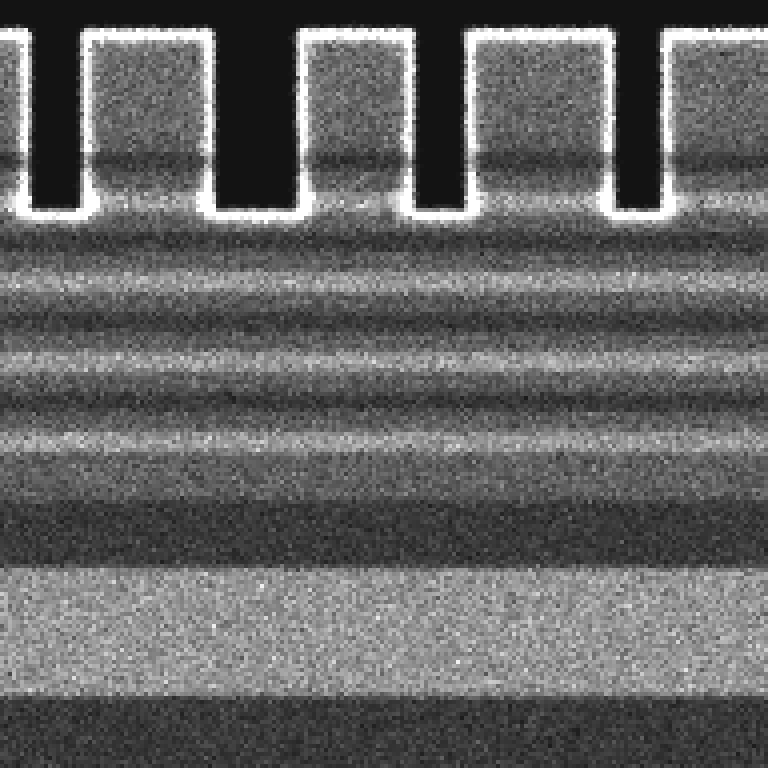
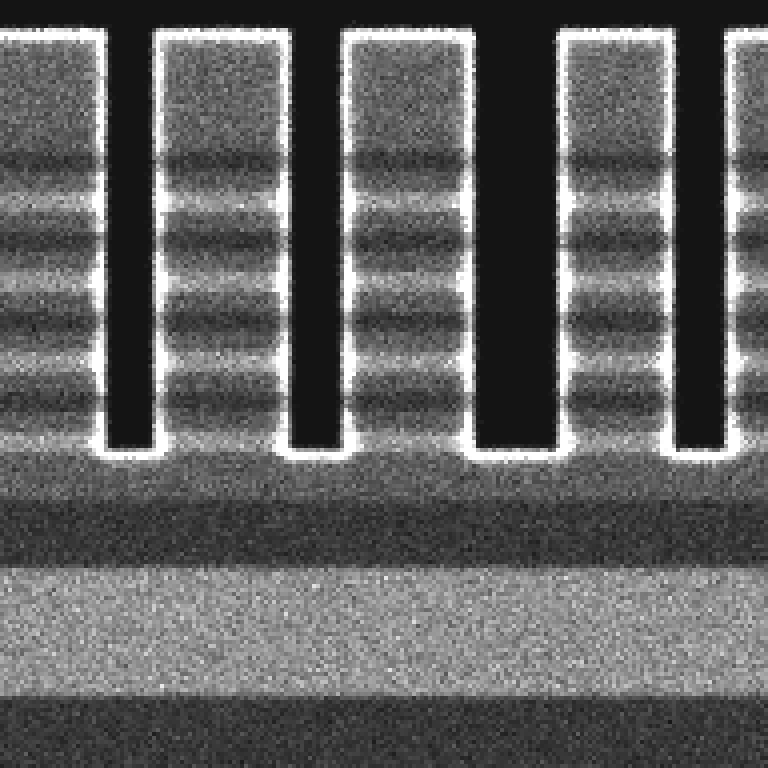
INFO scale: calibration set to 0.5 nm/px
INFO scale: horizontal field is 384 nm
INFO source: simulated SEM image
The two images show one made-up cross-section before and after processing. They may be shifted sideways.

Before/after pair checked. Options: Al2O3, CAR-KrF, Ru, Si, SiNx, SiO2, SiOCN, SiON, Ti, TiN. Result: removed Al2O3 and Si and SiOCN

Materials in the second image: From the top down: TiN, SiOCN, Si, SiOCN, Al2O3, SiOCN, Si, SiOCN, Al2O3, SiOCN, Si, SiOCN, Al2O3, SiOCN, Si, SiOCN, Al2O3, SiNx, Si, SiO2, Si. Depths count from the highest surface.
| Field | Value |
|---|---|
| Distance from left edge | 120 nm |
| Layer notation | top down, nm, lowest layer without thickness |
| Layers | TiN 50, SiOCN 10, Si 10, SiOCN 10, Al2O3 10, SiOCN 10, Si 10, SiOCN 10, Al2O3 10, SiOCN 10, Si 10, SiOCN 10, Al2O3 10, SiOCN 10, Si 10, SiOCN 10, Al2O3 10, SiNx 24, Si 34, SiO2 64, Si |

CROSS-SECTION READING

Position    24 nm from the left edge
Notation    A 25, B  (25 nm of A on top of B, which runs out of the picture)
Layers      TiN 50, SiOCN 10, Si 10, SiOCN 10, Al2O3 10, SiOCN 10, Si 10, SiOCN 10, Al2O3 10, SiOCN 10, Si 10, SiOCN 10, Al2O3 10, SiOCN 10, Si 10, SiOCN 10, Al2O3 10, SiNx 24, Si 34, SiO2 64, Si